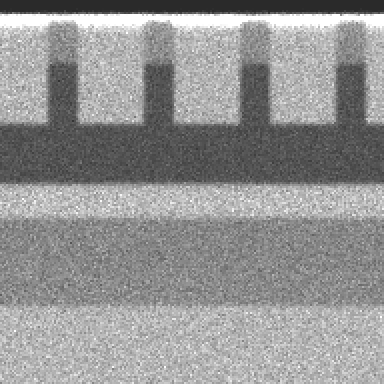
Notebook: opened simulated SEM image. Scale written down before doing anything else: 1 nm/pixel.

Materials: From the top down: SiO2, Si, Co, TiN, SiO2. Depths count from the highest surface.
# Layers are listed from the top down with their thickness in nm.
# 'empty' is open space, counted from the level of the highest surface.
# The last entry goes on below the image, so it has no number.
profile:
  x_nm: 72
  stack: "TiN 48, Si 120, Co 34, TiN 88, SiO2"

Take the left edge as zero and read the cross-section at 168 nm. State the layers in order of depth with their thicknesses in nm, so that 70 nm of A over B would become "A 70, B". TiN 48, Si 120, Co 34, TiN 88, SiO2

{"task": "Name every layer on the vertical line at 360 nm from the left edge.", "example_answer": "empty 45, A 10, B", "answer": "TiN 48, Si 120, Co 34, TiN 88, SiO2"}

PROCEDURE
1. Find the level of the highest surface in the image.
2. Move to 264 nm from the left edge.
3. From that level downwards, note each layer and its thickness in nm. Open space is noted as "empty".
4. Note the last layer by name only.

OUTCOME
TiN 48, Si 120, Co 34, TiN 88, SiO2